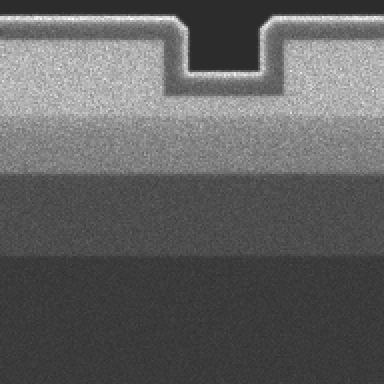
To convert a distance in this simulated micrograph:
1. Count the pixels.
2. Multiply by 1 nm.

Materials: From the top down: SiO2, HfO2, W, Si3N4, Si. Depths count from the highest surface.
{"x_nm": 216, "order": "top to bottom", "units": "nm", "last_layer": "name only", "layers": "empty 56, SiO2 24, HfO2 20, W 58, Si3N4 82, Si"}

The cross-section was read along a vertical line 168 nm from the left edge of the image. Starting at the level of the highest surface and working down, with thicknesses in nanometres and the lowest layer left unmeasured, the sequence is SiO2 80, HfO2 20, W 58, Si3N4 82, Si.